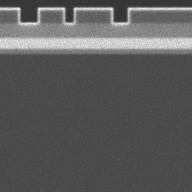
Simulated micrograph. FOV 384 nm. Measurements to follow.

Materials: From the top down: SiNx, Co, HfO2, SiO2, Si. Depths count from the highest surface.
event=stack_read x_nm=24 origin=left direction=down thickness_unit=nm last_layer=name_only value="SiNx 30, Co 30, HfO2 22, SiO2 10, Si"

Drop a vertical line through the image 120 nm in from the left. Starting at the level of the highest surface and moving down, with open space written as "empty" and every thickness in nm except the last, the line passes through SiNx 30, Co 30, HfO2 22, SiO2 10, Si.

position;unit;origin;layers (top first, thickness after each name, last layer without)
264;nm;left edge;SiNx 30, Co 30, HfO2 22, SiO2 10, Si